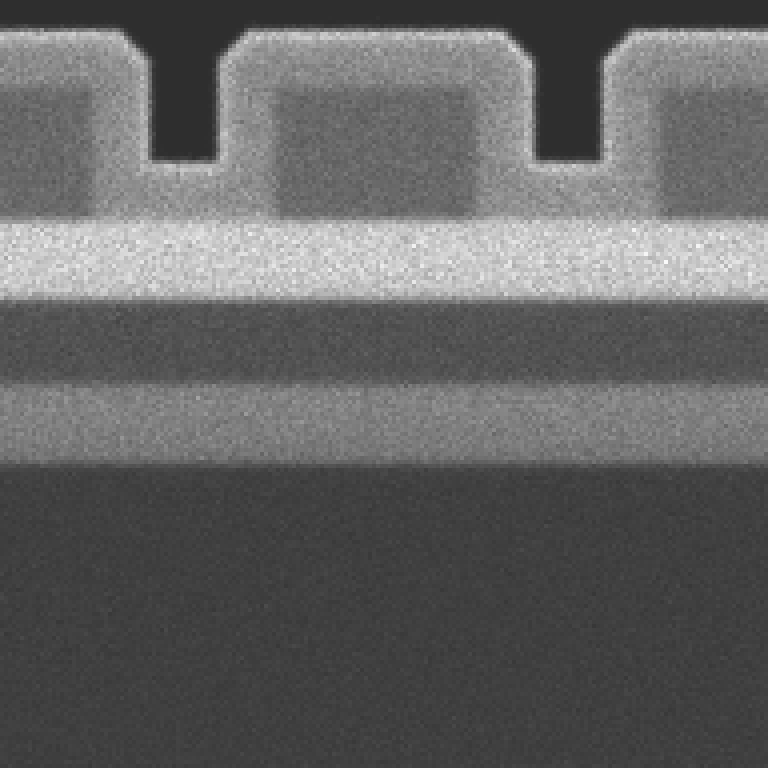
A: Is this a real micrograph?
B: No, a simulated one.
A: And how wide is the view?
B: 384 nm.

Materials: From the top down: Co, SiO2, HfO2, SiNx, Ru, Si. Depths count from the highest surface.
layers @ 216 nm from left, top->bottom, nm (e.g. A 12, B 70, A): Co 28, SiO2 66, HfO2 40, SiNx 42, Ru 40, Si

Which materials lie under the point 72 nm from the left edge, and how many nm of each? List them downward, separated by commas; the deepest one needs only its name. empty 14, Co 80, HfO2 40, SiNx 42, Ru 40, Si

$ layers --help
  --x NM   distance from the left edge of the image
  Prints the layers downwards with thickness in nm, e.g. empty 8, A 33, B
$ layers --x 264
empty 14, Co 80, HfO2 40, SiNx 42, Ru 40, Si